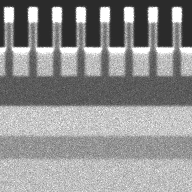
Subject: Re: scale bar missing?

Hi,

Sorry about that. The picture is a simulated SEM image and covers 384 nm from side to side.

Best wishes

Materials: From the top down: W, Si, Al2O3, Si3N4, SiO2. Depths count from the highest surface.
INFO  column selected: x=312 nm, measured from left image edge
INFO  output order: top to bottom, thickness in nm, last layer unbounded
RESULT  W 28, Si 168, Al2O3 60, Si3N4 46, SiO2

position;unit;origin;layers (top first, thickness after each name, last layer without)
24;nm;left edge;W 28, Si 168, Al2O3 60, Si3N4 46, SiO2